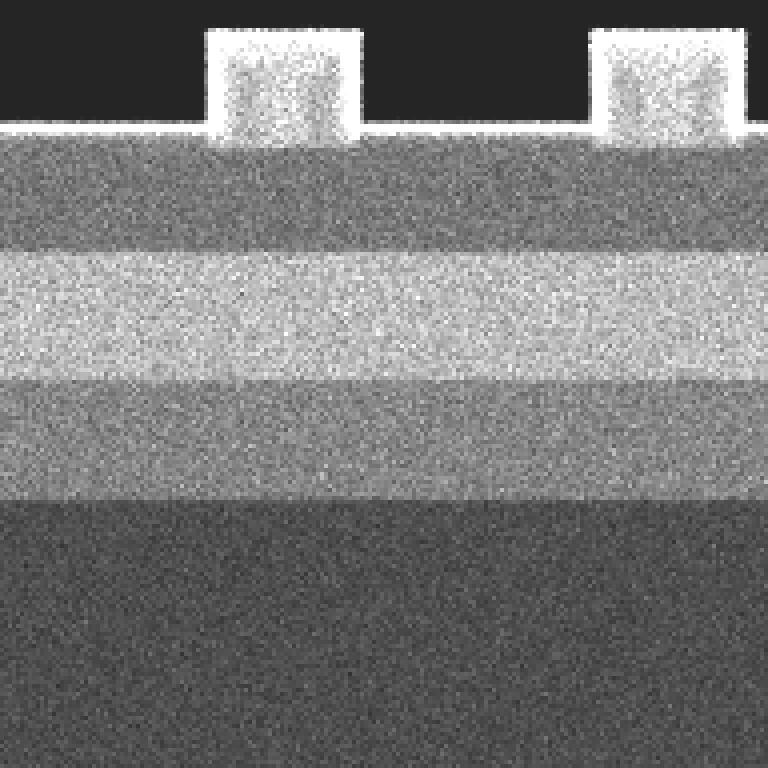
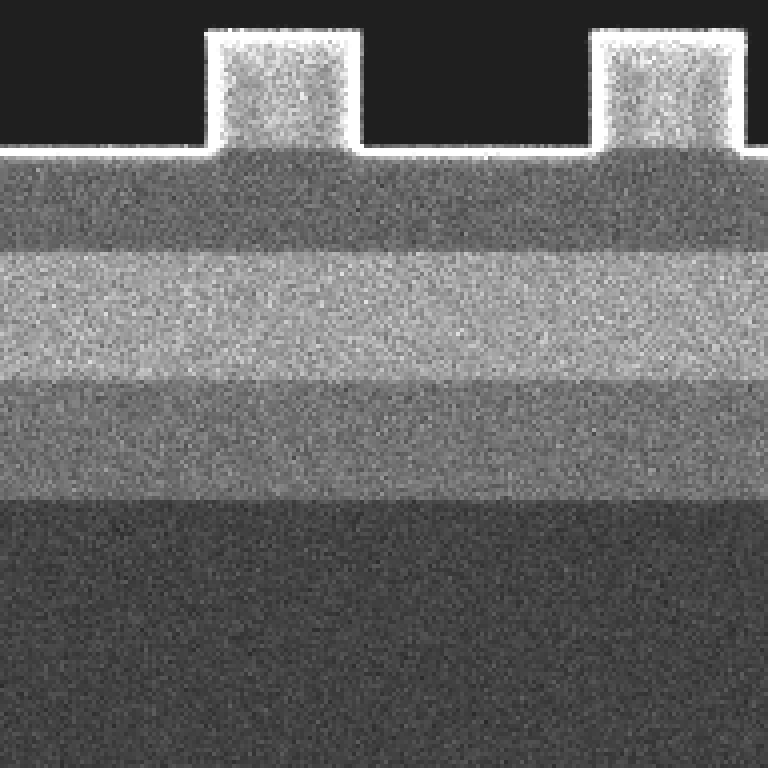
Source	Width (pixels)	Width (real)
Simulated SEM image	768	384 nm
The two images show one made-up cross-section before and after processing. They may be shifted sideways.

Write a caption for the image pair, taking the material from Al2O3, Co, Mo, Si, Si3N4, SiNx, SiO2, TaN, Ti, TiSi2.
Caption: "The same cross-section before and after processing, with SiNx removed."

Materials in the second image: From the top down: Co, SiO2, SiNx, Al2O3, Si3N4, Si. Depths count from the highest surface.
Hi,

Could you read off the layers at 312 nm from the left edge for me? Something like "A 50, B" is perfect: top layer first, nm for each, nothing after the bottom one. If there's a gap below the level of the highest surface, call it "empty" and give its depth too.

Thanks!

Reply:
Co 16, SiO2 42, SiNx 52, Al2O3 64, Si3N4 60, Si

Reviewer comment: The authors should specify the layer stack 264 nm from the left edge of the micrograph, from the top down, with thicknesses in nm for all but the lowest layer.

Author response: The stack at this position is empty 58, SiNx 52, Al2O3 64, Si3N4 60, Si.